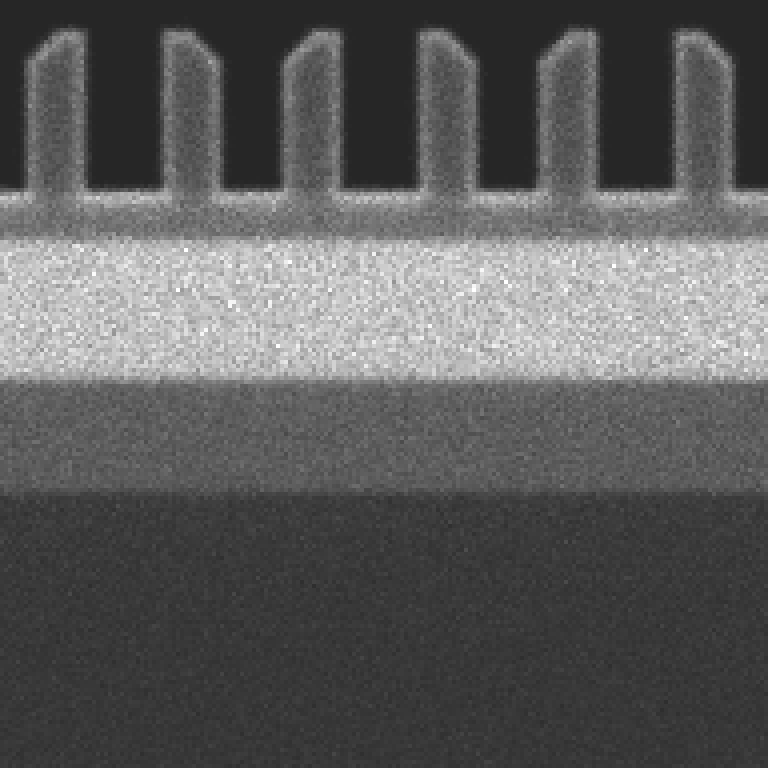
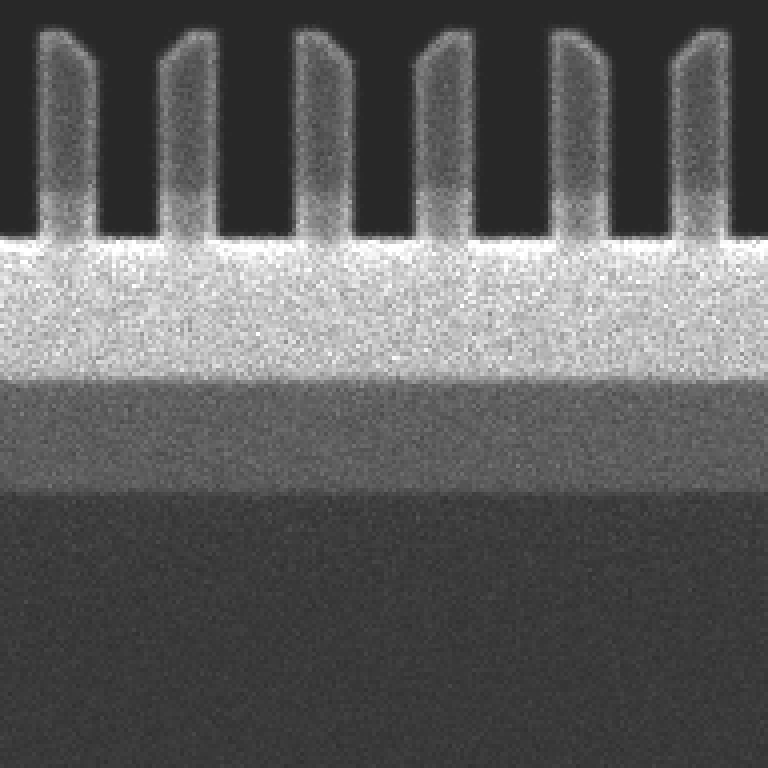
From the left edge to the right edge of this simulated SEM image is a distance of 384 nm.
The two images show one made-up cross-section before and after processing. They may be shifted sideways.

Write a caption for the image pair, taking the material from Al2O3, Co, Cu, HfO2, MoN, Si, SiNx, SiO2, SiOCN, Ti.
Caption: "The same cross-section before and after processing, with Al2O3 removed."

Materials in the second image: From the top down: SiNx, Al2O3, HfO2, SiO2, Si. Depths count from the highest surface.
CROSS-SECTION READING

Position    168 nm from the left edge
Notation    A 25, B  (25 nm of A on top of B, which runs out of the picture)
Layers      empty 8, SiNx 72, Al2O3 24, HfO2 70, SiO2 56, Si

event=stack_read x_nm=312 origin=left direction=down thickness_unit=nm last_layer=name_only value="empty 104, HfO2 70, SiO2 56, Si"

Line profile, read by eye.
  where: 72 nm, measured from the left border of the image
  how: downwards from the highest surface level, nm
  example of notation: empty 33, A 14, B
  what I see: empty 104, HfO2 70, SiO2 56, Si